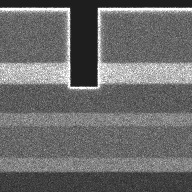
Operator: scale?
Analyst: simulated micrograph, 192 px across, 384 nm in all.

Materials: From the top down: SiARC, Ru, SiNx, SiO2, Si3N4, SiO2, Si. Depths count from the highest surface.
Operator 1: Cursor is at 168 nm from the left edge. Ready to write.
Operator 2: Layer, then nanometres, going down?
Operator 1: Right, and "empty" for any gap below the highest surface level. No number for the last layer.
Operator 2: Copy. empty 158, SiNx 52, SiO2 26, Si3N4 64, SiO2 28, Si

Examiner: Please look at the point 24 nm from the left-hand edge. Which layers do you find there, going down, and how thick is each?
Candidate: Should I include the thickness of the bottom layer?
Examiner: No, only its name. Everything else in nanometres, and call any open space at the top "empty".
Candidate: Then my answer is SiARC 110, Ru 42, SiNx 58, SiO2 26, Si3N4 64, SiO2 28, Si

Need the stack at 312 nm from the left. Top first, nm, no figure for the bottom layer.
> SiARC 110, Ru 42, SiNx 58, SiO2 26, Si3N4 64, SiO2 28, Si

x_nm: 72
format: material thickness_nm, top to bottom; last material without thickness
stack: SiARC 110, Ru 42, SiNx 58, SiO2 26, Si3N4 64, SiO2 28, Si